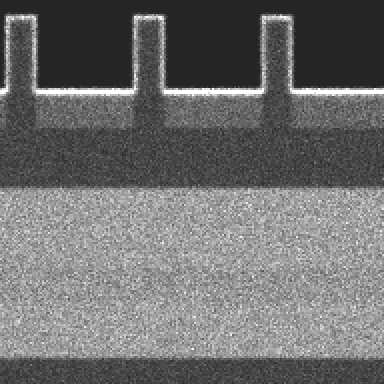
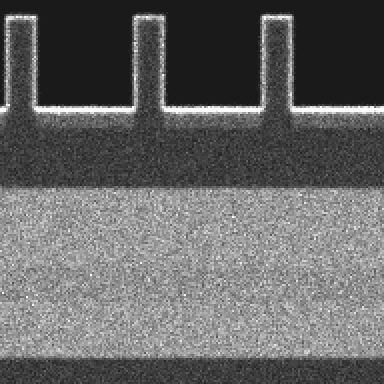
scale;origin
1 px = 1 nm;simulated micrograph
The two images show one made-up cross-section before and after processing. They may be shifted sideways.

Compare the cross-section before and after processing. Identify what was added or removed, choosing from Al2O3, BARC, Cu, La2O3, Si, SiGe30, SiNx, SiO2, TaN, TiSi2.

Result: SiNx removed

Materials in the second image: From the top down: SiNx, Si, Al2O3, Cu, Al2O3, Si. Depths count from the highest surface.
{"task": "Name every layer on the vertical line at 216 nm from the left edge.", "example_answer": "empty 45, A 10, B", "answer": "empty 92, SiNx 20, Si 60, Al2O3 80, Cu 34, Al2O3 56, Si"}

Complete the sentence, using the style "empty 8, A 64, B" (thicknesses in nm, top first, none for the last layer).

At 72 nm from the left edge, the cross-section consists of empty 92, SiNx 20, Si 60, Al2O3 80, Cu 34, Al2O3 56, Si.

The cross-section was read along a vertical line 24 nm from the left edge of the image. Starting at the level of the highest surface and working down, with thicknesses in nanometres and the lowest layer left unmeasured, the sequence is Si 172, Al2O3 80, Cu 34, Al2O3 56, Si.